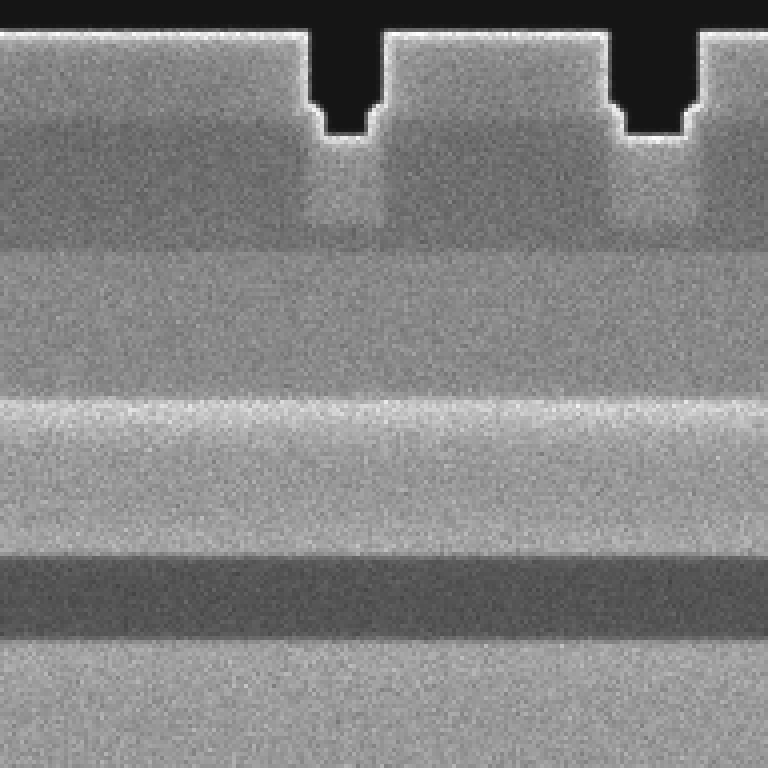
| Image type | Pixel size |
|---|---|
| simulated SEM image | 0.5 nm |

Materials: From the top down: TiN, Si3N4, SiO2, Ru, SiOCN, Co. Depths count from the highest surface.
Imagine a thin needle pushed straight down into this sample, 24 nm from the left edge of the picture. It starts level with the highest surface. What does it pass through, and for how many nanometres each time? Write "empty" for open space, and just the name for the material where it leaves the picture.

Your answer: TiN 44, Si3N4 66, SiO2 74, Ru 78, SiOCN 42, Co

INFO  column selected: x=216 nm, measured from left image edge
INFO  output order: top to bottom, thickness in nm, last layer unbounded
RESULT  TiN 44, Si3N4 66, SiO2 74, Ru 78, SiOCN 42, Co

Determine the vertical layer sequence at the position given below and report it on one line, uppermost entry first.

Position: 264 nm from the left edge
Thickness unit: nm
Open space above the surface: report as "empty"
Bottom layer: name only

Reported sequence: TiN 44, Si3N4 66, SiO2 74, Ru 78, SiOCN 42, Co